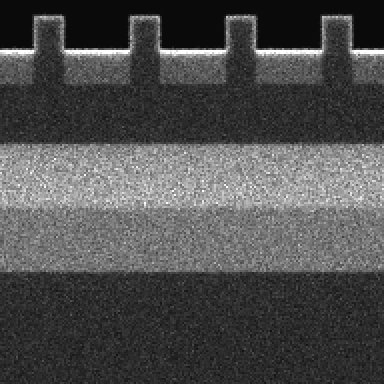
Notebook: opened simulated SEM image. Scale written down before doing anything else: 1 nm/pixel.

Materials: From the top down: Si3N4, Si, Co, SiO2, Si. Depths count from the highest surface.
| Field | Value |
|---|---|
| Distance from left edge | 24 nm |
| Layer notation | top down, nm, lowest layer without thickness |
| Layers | empty 34, Si3N4 34, Si 60, Co 64, SiO2 64, Si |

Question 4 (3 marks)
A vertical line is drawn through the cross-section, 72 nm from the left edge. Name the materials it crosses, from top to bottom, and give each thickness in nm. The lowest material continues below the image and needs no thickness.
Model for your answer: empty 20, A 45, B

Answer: empty 34, Si3N4 34, Si 60, Co 64, SiO2 64, Si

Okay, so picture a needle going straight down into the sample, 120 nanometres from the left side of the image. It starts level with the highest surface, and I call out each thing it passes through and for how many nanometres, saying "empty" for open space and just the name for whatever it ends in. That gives empty 34, Si3N4 34, Si 60, Co 64, SiO2 64, Si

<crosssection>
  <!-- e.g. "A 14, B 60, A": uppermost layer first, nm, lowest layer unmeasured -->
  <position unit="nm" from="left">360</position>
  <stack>empty 34, Si3N4 34, Si 60, Co 64, SiO2 64, Si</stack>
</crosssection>